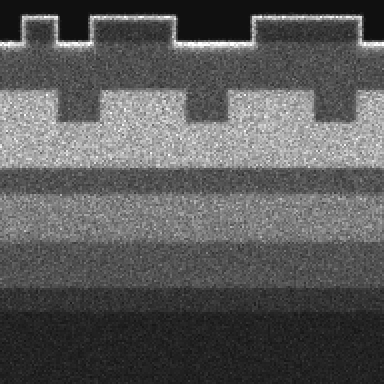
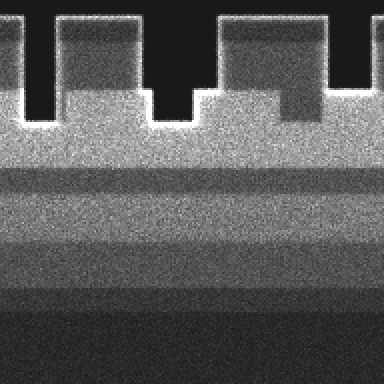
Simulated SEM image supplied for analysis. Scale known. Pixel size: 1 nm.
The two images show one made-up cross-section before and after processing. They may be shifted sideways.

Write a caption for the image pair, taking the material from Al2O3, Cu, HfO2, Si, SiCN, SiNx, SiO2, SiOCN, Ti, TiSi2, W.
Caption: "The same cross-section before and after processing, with SiO2 removed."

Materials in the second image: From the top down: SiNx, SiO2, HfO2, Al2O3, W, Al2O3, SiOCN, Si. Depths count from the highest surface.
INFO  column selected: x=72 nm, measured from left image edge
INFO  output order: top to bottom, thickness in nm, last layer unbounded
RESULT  SiNx 26, SiO2 48, HfO2 78, Al2O3 26, W 48, Al2O3 46, SiOCN 24, Si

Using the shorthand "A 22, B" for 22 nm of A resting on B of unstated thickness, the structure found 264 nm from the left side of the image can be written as SiNx 26, SiO2 48, HfO2 78, Al2O3 26, W 48, Al2O3 46, SiOCN 24, Si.